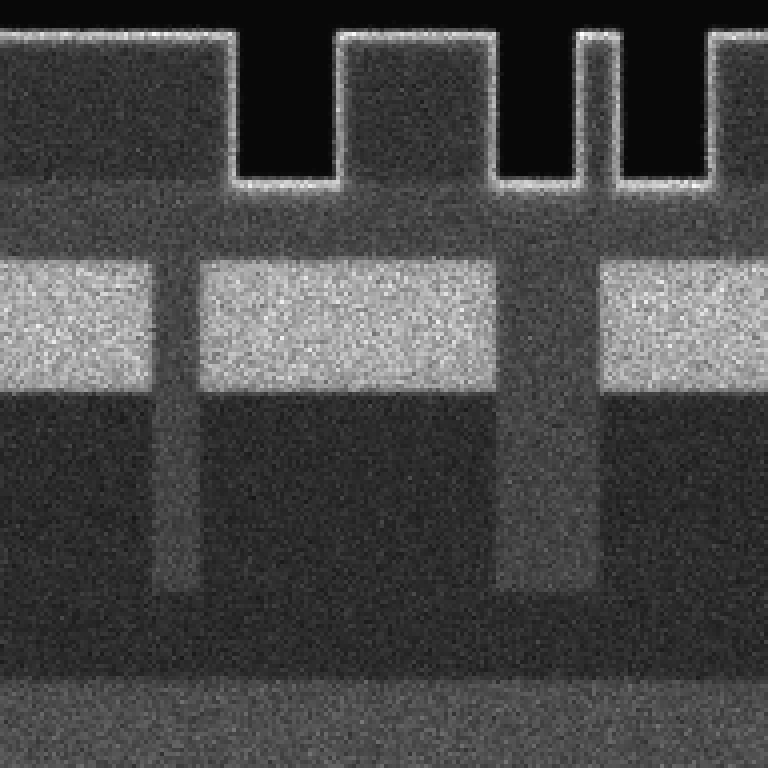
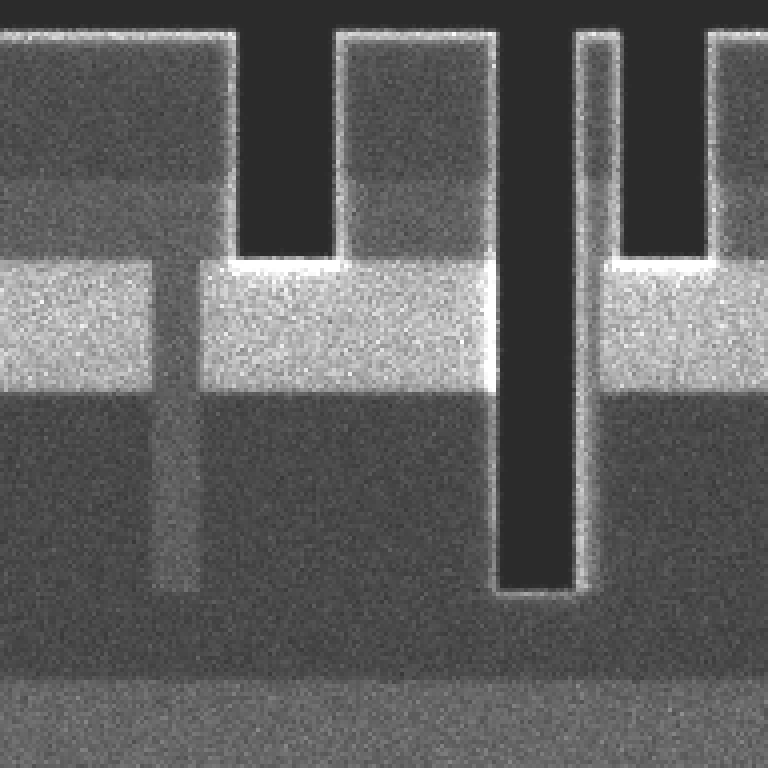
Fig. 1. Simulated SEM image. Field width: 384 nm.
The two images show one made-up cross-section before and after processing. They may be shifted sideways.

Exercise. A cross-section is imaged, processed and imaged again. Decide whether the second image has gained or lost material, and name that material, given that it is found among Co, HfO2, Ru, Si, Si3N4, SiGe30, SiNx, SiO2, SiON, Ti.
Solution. removed: SiO2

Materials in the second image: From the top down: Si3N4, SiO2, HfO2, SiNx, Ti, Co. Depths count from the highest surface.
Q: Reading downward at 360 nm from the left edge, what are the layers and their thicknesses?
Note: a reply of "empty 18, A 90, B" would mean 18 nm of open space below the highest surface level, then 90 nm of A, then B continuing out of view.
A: Si3N4 74, SiO2 40, HfO2 66, SiNx 70, Ti 74, Co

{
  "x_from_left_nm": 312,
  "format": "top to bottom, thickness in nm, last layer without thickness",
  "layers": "empty 114, HfO2 66, SiNx 70, Ti 74, Co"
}